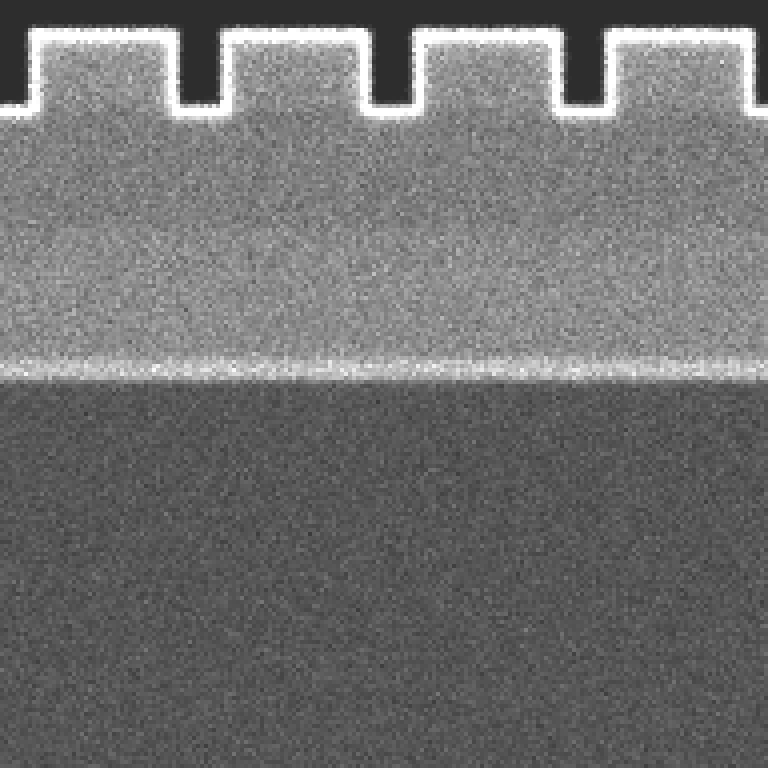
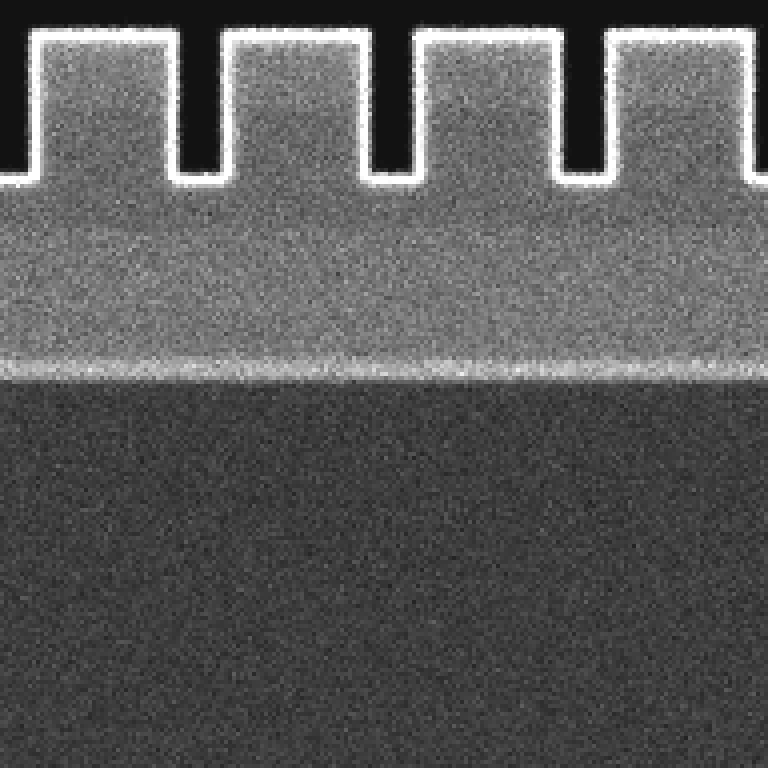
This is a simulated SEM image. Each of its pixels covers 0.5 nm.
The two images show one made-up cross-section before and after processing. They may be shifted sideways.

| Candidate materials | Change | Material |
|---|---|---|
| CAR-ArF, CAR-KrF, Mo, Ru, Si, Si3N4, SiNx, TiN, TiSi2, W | removed | SiNx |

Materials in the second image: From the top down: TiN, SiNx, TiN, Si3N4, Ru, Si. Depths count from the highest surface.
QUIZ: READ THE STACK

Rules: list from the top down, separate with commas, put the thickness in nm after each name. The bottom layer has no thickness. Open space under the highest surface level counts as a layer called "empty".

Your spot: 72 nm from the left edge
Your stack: TiN 38, SiNx 60, TiN 22, Si3N4 44, Ru 10, Si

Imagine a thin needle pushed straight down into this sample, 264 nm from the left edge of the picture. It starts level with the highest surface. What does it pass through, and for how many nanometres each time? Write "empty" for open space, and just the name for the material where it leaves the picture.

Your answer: TiN 38, SiNx 60, TiN 22, Si3N4 44, Ru 10, Si